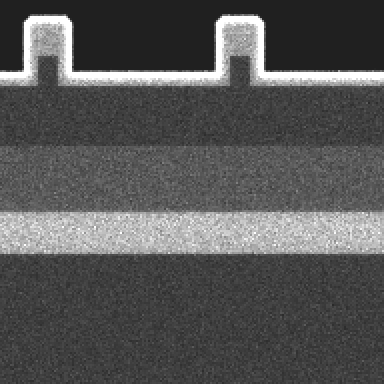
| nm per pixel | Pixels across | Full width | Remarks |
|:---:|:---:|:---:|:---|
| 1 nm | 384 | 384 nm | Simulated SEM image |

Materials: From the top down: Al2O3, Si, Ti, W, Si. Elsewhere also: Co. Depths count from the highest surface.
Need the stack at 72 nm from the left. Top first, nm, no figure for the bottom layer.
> empty 56, Al2O3 14, Si 60, Ti 66, W 42, Si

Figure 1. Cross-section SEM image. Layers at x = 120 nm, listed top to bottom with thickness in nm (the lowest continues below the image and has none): empty 56, Al2O3 14, Si 60, Ti 66, W 42, Si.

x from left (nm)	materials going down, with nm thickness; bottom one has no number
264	empty 56, Al2O3 14, Si 60, Ti 66, W 42, Si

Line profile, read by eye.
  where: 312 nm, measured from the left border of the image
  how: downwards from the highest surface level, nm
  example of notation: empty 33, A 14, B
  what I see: empty 56, Al2O3 14, Si 60, Ti 66, W 42, Si